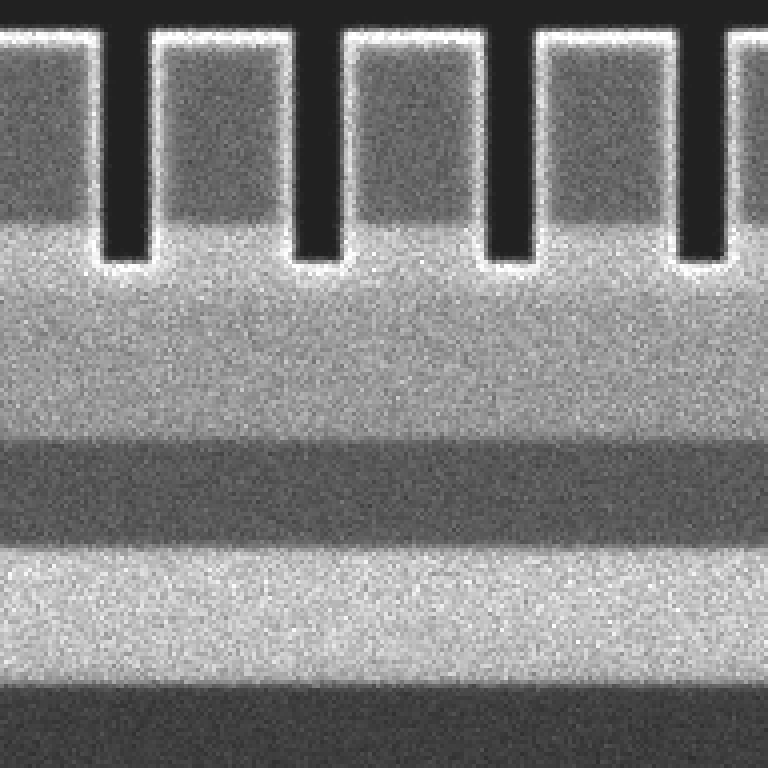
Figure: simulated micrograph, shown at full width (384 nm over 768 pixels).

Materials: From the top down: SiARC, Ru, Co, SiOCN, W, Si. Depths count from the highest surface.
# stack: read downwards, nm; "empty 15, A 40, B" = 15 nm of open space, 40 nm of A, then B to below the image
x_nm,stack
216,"SiARC 96, Ru 34, Co 74, SiOCN 54, W 68, Si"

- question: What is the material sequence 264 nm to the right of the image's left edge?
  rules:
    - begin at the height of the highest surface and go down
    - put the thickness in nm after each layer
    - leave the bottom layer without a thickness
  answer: empty 116, Ru 14, Co 74, SiOCN 54, W 68, Si